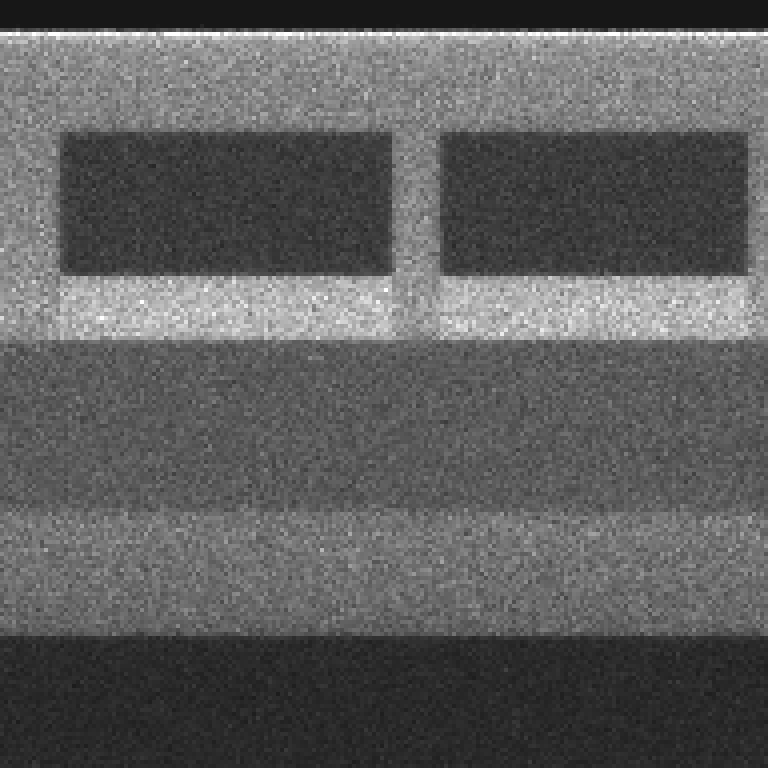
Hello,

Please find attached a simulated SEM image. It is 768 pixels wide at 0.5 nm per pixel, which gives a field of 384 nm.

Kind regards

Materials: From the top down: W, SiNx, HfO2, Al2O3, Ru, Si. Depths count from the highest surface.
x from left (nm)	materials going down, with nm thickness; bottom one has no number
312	W 50, SiNx 72, HfO2 32, Al2O3 86, Ru 62, Si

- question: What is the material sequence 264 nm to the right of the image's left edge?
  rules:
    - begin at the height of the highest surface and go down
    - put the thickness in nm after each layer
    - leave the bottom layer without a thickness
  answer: W 50, SiNx 72, HfO2 32, Al2O3 86, Ru 62, Si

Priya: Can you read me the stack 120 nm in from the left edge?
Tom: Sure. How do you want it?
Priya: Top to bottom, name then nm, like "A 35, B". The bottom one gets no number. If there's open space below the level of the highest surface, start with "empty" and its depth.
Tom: W 50, SiNx 72, HfO2 32, Al2O3 86, Ru 62, Si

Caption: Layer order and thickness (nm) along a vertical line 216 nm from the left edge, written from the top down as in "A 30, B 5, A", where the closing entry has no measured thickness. W 154, Al2O3 86, Ru 62, Si